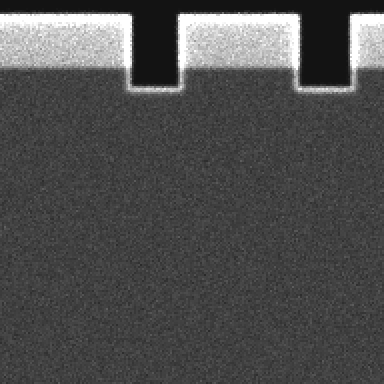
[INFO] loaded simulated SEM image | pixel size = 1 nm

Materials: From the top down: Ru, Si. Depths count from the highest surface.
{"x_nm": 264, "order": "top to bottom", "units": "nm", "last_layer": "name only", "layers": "Ru 52, Si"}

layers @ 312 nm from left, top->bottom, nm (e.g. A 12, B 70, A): empty 72, Si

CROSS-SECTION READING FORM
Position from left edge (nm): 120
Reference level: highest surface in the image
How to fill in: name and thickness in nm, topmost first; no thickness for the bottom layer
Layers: Ru 52, Si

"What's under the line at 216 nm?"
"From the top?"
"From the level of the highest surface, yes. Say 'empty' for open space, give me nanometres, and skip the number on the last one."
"Ru 52, Si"